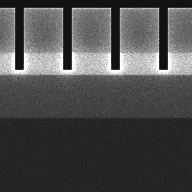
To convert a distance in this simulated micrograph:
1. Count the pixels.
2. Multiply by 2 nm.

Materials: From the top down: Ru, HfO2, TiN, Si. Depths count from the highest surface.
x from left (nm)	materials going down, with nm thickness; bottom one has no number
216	Ru 90, HfO2 44, TiN 86, Si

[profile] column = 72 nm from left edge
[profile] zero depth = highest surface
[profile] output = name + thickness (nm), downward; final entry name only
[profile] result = Ru 90, HfO2 44, TiN 86, Si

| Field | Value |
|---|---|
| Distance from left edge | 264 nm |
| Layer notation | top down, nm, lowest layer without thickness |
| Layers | Ru 90, HfO2 44, TiN 86, Si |